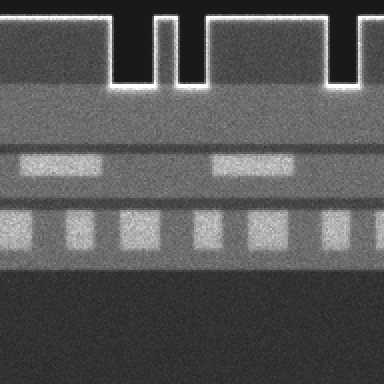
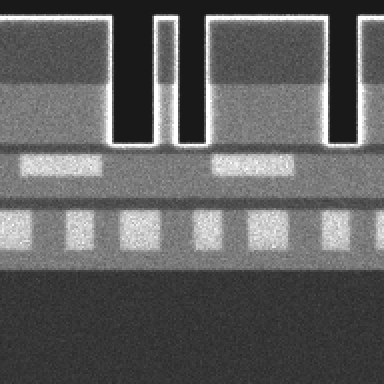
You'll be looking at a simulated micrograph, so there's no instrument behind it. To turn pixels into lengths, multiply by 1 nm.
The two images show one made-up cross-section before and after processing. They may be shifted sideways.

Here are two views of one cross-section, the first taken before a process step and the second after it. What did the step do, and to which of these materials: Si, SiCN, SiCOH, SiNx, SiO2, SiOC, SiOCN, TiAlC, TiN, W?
It removed SiO2.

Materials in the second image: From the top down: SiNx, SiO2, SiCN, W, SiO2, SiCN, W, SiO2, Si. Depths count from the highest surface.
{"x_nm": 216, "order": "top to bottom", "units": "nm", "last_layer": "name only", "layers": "SiNx 68, SiO2 60, SiCN 10, W 22, SiO2 22, SiCN 12, W 40, SiO2 20, Si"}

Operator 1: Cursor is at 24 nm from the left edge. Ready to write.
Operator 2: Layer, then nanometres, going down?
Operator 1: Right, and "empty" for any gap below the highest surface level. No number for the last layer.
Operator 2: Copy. SiNx 68, SiO2 60, SiCN 10, W 22, SiO2 22, SiCN 12, W 40, SiO2 20, Si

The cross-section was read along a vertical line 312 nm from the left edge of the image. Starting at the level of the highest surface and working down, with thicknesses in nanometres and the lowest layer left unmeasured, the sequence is SiNx 68, SiO2 60, SiCN 10, SiO2 44, SiCN 12, SiO2 60, Si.